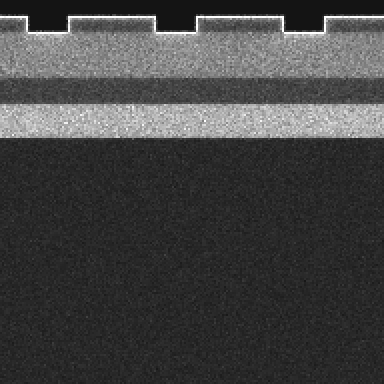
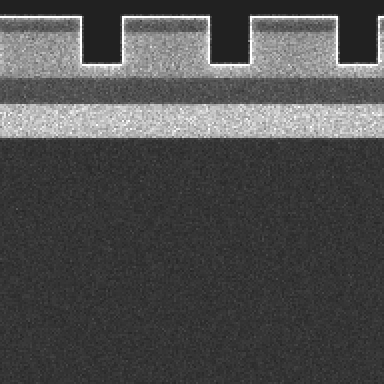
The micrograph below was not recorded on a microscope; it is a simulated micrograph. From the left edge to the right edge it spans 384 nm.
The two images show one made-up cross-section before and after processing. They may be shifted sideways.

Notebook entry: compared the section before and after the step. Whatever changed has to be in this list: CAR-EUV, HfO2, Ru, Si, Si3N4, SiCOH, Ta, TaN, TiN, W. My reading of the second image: W removed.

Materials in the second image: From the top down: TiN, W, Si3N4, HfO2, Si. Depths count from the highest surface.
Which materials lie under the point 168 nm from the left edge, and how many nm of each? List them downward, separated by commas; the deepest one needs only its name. TiN 16, W 46, Si3N4 26, HfO2 34, Si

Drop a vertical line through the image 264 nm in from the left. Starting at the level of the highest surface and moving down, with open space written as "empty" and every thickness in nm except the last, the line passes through TiN 16, W 46, Si3N4 26, HfO2 34, Si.